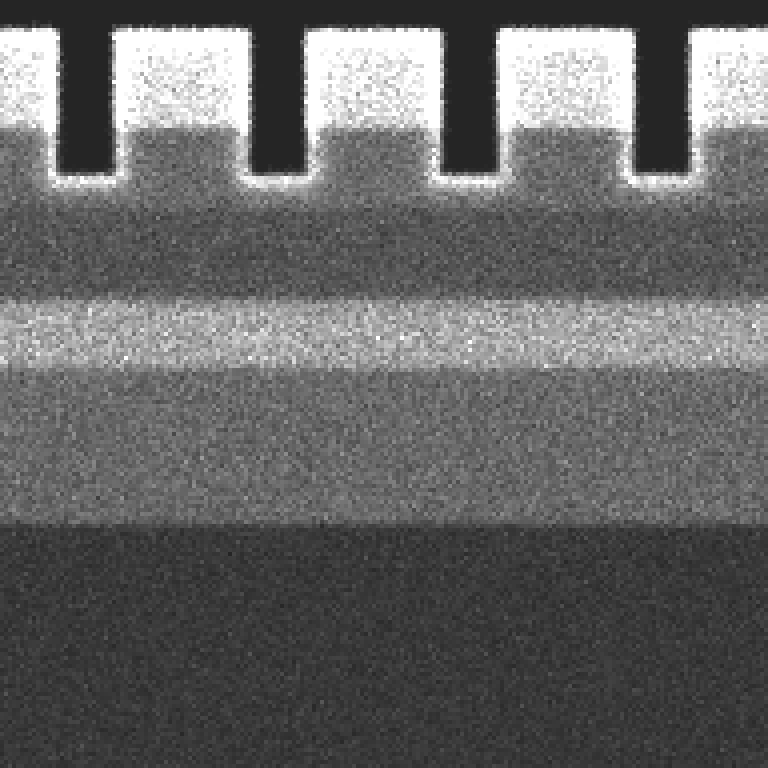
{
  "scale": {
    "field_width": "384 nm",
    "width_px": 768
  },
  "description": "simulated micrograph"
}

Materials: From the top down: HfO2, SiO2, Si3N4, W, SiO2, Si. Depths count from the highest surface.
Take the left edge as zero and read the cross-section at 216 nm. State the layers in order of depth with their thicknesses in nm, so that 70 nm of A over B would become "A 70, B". HfO2 48, SiO2 40, Si3N4 46, W 34, SiO2 78, Si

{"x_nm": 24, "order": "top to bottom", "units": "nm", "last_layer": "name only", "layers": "HfO2 48, SiO2 40, Si3N4 46, W 34, SiO2 78, Si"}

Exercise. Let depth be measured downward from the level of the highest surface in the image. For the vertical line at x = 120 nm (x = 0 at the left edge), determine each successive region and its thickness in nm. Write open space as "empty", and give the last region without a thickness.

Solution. HfO2 48, SiO2 40, Si3N4 46, W 34, SiO2 78, Si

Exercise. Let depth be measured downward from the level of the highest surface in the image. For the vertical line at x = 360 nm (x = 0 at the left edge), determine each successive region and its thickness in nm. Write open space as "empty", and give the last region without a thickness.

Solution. HfO2 48, SiO2 40, Si3N4 46, W 34, SiO2 78, Si